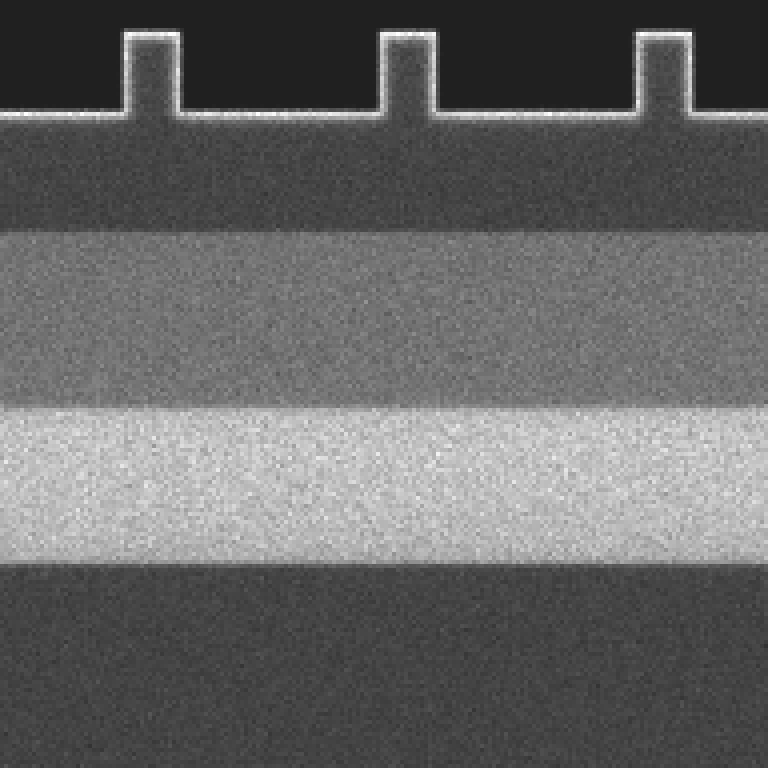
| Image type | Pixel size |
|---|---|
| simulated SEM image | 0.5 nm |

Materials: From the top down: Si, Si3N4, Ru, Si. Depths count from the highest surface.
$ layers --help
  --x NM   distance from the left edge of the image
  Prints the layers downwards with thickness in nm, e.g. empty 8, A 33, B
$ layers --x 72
Si 100, Si3N4 88, Ru 78, Si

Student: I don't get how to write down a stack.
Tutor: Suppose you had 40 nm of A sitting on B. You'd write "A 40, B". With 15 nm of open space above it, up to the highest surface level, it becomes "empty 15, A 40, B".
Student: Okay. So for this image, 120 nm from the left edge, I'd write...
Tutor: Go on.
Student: empty 40, Si 60, Si3N4 88, Ru 78, Si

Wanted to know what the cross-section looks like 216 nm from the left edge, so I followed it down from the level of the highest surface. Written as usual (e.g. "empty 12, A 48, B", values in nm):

Si 100, Si3N4 88, Ru 78, Si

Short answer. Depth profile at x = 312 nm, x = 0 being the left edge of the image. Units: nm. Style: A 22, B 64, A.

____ empty 40, Si 60, Si3N4 88, Ru 78, Si